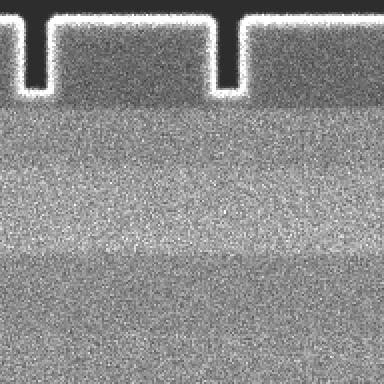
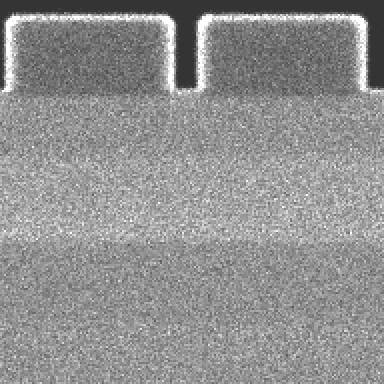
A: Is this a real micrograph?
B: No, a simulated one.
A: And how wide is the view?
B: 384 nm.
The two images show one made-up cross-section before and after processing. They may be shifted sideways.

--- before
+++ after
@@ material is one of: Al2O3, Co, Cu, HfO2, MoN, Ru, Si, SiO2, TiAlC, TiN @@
SiO2 removed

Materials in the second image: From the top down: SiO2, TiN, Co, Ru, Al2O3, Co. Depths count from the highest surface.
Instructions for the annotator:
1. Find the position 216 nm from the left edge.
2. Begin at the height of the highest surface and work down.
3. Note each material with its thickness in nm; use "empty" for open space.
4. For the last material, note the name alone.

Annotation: TiN 80, Co 60, Ru 86, Al2O3 80, Co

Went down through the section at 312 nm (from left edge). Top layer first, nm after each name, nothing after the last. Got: TiN 80, Co 60, Ru 86, Al2O3 80, Co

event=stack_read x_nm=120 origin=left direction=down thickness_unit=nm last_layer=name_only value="TiN 80, Co 60, Ru 86, Al2O3 80, Co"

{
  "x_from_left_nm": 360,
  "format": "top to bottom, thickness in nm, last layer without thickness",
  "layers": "empty 2, SiO2 72, TiN 6, Co 60, Ru 86, Al2O3 80, Co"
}